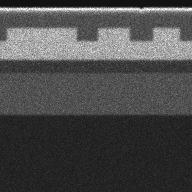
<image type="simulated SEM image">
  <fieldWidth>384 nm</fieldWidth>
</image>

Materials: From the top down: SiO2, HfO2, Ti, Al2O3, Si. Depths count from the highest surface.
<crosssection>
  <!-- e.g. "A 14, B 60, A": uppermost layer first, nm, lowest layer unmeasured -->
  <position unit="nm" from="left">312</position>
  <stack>SiO2 40, HfO2 64, Ti 26, Al2O3 84, Si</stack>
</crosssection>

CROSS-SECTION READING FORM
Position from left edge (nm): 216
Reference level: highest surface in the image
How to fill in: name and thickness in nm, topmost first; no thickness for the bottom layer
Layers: SiO2 40, HfO2 64, Ti 26, Al2O3 84, Si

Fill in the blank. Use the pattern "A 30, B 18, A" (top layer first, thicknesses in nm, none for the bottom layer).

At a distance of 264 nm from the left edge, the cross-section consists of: SiO2 66, HfO2 38, Ti 26, Al2O3 84, Si